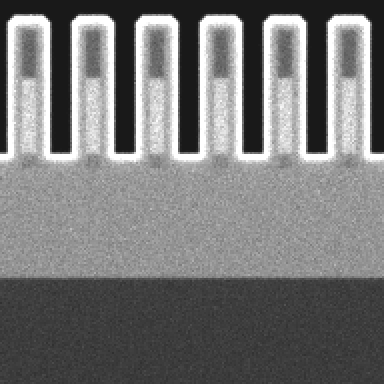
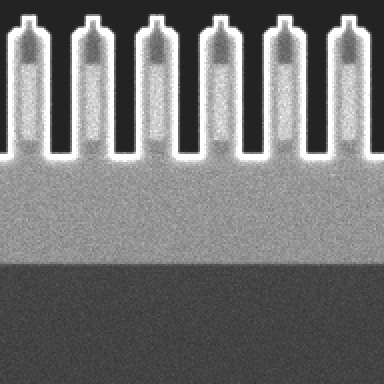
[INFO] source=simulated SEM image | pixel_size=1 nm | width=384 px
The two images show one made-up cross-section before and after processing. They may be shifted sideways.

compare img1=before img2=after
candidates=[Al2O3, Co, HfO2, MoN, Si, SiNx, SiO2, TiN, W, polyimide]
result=removed:SiO2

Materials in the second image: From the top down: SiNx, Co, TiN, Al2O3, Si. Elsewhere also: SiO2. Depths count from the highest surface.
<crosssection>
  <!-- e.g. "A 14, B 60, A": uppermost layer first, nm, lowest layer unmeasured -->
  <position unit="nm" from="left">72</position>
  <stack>empty 18, SiO2 120, Al2O3 110, Si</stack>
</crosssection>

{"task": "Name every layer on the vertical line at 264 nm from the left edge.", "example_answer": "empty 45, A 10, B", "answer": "empty 18, SiO2 120, Al2O3 110, Si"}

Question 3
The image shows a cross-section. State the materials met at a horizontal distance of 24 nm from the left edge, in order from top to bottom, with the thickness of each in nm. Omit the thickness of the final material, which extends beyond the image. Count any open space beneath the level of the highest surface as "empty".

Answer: SiNx 48, Co 76, TiN 14, Al2O3 110, Si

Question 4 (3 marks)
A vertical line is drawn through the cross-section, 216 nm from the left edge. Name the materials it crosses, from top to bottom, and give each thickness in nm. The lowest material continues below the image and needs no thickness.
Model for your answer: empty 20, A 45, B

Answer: SiNx 48, Co 76, TiN 14, Al2O3 110, Si